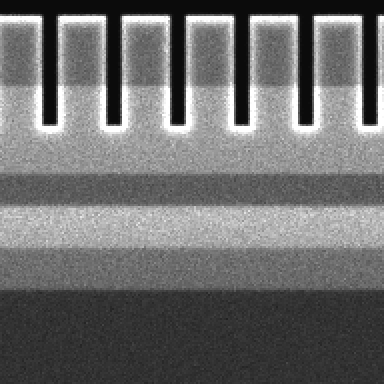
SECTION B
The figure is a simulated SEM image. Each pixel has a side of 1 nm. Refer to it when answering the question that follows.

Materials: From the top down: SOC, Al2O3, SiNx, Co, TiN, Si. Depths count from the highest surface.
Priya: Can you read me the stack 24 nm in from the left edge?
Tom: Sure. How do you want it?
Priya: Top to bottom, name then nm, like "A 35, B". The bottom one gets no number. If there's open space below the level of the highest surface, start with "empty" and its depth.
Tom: SOC 70, Al2O3 88, SiNx 32, Co 42, TiN 42, Si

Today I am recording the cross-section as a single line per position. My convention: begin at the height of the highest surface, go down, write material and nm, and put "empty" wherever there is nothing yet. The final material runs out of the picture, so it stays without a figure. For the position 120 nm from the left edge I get empty 110, Al2O3 48, SiNx 32, Co 42, TiN 42, Si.